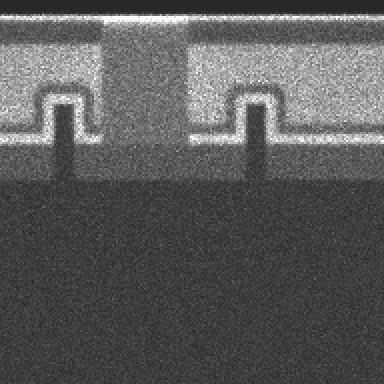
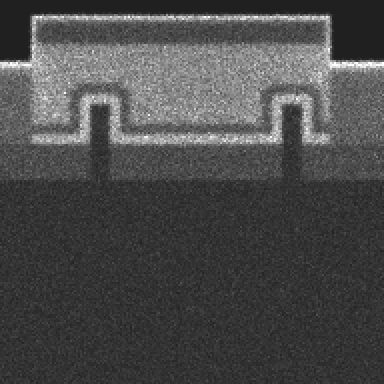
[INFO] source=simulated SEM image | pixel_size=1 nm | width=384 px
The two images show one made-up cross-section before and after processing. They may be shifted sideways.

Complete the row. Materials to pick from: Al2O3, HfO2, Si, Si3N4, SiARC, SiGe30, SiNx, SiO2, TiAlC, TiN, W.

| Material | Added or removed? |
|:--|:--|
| SiO2 | removed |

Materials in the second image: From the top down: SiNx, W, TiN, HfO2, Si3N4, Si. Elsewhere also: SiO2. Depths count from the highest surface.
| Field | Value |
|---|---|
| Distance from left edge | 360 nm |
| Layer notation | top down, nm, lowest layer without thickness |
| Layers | empty 46, SiO2 82, Si3N4 36, Si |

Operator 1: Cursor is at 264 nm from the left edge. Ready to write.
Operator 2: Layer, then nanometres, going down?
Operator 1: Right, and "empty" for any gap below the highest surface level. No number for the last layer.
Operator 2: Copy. SiNx 28, W 46, TiN 44, HfO2 10, Si3N4 36, Si